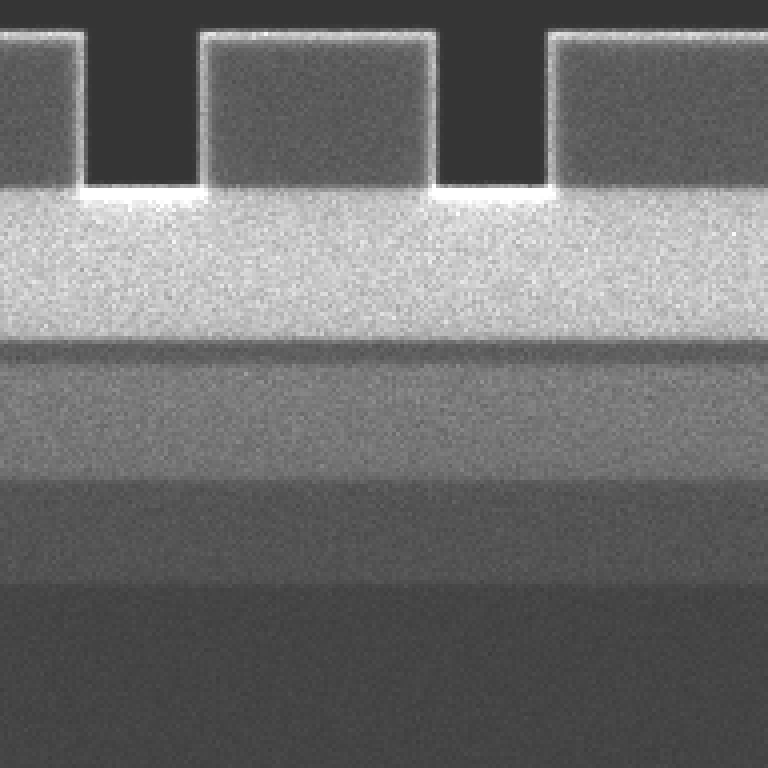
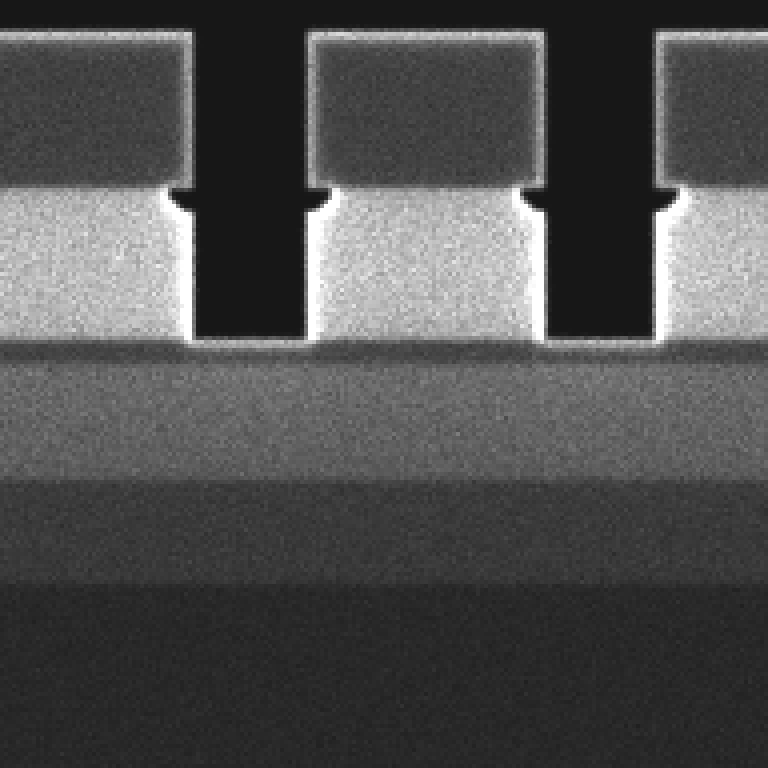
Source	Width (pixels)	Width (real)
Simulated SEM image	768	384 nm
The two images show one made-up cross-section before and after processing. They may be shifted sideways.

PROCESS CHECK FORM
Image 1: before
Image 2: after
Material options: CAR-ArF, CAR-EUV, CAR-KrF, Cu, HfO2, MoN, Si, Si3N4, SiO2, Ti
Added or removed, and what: removed, HfO2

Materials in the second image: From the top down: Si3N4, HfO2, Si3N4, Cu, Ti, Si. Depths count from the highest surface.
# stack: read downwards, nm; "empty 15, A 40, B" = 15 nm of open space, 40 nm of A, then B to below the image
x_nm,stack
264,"Si3N4 78, empty 10, HfO2 66, Si3N4 12, Cu 58, Ti 52, Si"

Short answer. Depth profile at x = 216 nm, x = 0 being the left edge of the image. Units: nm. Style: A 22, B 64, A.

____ Si3N4 78, HfO2 76, Si3N4 12, Cu 58, Ti 52, Si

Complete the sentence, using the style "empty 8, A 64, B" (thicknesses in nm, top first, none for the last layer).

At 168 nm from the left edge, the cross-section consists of Si3N4 78, HfO2 76, Si3N4 12, Cu 58, Ti 52, Si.